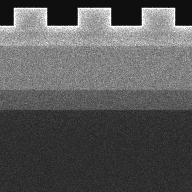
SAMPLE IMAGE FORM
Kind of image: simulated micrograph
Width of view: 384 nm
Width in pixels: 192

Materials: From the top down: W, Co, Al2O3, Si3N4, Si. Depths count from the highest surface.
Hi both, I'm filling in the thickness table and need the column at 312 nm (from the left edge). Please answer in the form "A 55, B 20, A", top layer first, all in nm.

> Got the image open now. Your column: W 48, Co 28, Al2O3 88, Si3N4 40, Si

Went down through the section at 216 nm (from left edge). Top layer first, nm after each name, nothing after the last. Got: W 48, Co 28, Al2O3 88, Si3N4 40, Si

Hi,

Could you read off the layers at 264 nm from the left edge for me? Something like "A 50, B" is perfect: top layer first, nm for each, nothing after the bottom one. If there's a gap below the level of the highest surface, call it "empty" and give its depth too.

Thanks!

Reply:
empty 36, W 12, Co 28, Al2O3 88, Si3N4 40, Si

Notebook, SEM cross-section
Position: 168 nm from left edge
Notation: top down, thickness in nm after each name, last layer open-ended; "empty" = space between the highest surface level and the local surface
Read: W 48, Co 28, Al2O3 88, Si3N4 40, Si